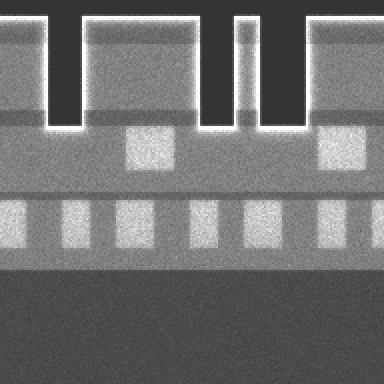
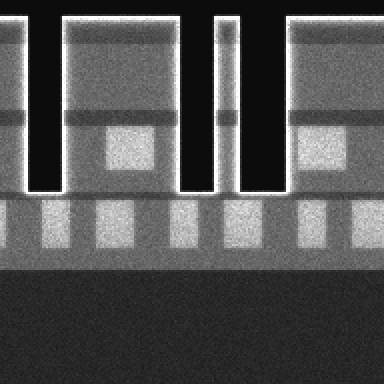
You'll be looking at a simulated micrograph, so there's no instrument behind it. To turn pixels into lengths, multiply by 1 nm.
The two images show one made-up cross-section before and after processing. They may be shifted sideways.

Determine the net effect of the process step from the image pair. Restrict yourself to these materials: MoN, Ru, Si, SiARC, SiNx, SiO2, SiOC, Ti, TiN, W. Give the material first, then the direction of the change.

SiO2: removed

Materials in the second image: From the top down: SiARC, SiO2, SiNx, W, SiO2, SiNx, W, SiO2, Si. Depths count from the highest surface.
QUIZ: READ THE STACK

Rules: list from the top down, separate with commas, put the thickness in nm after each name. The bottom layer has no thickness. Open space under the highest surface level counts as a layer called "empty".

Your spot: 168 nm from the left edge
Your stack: SiARC 28, SiO2 66, SiNx 16, SiO2 66, SiNx 8, SiO2 70, Si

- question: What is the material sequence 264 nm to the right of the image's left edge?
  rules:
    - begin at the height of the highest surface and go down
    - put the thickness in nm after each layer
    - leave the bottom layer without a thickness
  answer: empty 176, SiNx 8, SiO2 70, Si